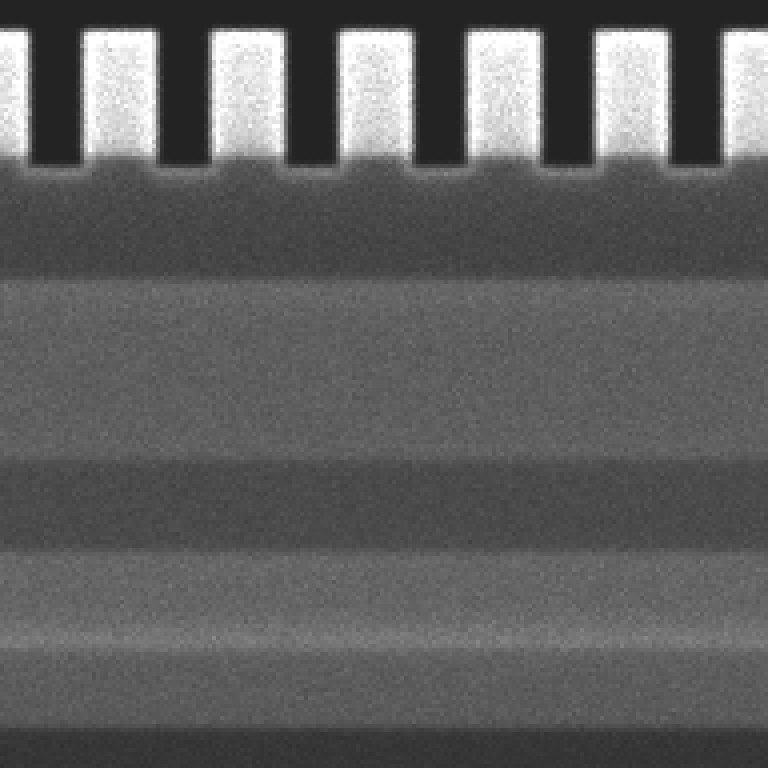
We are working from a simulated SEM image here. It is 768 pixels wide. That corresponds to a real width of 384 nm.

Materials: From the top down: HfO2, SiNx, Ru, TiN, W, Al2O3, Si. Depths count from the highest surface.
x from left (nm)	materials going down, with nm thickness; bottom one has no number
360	empty 68, SiNx 56, Ru 90, TiN 46, W 48, Al2O3 40, Si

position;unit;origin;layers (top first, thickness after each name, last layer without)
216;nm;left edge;empty 68, SiNx 56, Ru 90, TiN 46, W 48, Al2O3 40, Si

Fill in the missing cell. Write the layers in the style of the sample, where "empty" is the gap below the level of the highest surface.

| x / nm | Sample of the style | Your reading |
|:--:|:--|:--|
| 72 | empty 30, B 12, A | HfO2 62, SiNx 62, Ru 90, TiN 46, W 48, Al2O3 40, Si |